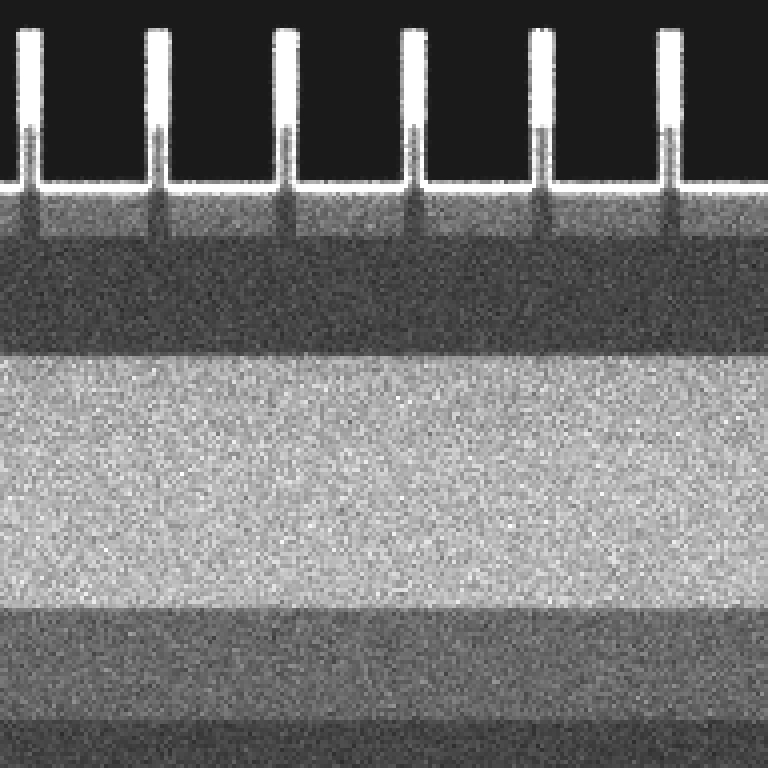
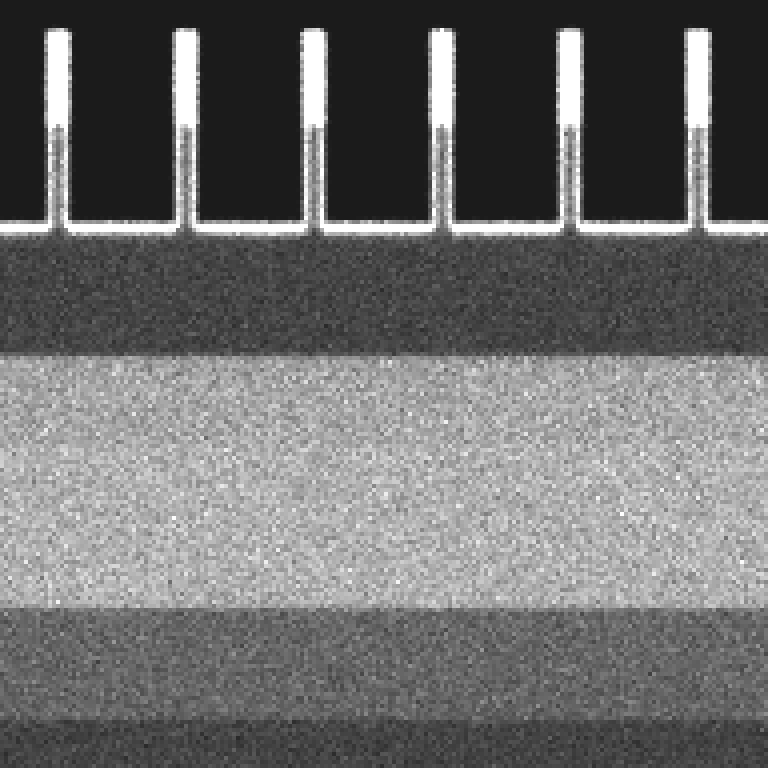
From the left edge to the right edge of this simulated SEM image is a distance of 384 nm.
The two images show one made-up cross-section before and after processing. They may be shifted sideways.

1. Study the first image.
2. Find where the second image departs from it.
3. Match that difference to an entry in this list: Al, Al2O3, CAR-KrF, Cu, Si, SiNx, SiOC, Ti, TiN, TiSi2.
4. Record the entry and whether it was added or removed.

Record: SiNx / removed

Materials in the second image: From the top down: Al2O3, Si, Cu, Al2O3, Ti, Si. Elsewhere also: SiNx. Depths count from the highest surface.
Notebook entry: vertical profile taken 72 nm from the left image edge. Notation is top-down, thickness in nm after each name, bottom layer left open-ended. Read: empty 96, SiNx 6, Si 60, Cu 44, Al2O3 82, Ti 56, Si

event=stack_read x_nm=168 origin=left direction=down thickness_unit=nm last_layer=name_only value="empty 96, SiNx 6, Si 60, Cu 44, Al2O3 82, Ti 56, Si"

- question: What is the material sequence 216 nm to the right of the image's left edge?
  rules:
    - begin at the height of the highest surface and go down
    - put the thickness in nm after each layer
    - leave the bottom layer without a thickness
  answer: Al2O3 46, Si 116, Cu 44, Al2O3 82, Ti 56, Si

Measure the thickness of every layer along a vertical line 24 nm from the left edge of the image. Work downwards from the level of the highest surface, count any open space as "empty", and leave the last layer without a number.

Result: Al2O3 46, Si 116, Cu 44, Al2O3 82, Ti 56, Si